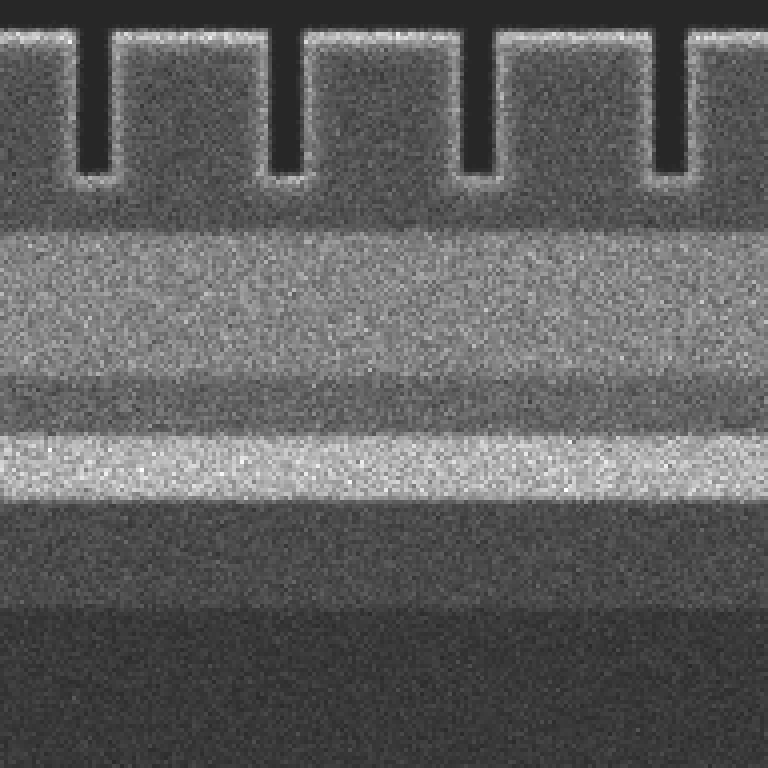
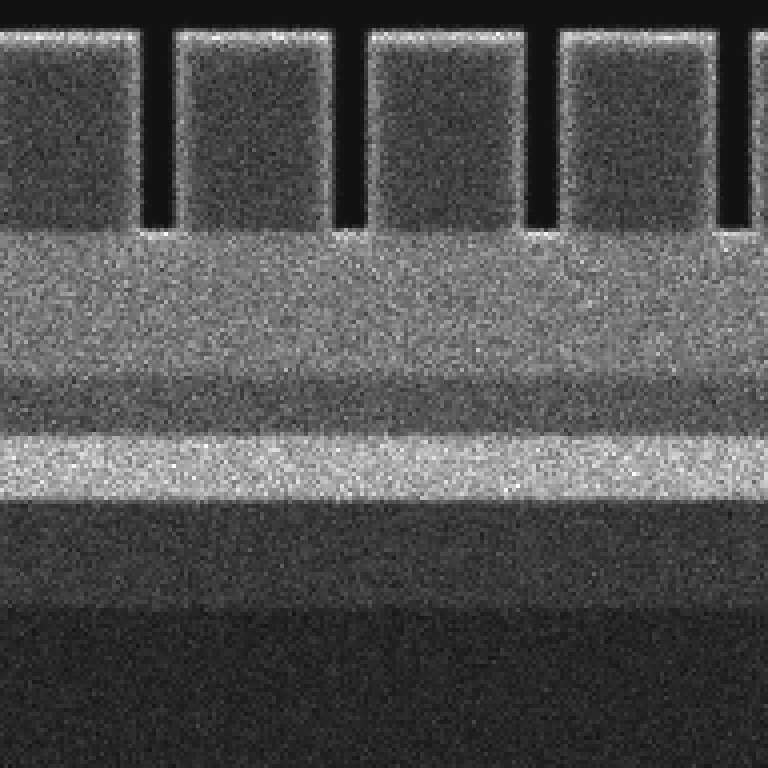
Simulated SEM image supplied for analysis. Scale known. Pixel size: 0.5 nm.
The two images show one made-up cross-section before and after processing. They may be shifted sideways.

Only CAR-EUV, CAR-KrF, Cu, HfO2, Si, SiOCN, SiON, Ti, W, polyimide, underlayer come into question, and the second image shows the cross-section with underlayer removed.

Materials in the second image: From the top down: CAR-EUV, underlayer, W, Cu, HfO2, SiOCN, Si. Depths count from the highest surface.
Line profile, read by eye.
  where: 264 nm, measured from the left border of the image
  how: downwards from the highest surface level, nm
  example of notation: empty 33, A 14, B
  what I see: empty 100, W 72, Cu 30, HfO2 32, SiOCN 54, Si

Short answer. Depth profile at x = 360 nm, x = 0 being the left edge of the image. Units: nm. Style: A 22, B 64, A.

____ empty 100, W 72, Cu 30, HfO2 32, SiOCN 54, Si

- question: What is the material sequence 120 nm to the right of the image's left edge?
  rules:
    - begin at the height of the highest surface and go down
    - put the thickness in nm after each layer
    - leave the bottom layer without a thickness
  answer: CAR-EUV 72, underlayer 28, W 72, Cu 30, HfO2 32, SiOCN 54, Si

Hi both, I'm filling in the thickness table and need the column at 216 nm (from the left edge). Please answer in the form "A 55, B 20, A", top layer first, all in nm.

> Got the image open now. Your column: CAR-EUV 72, underlayer 28, W 72, Cu 30, HfO2 32, SiOCN 54, Si